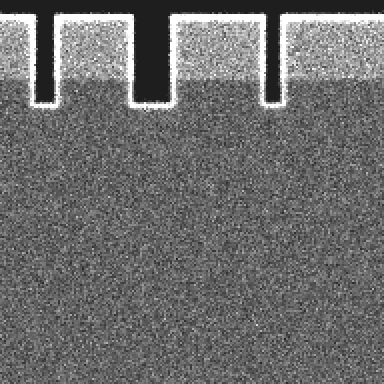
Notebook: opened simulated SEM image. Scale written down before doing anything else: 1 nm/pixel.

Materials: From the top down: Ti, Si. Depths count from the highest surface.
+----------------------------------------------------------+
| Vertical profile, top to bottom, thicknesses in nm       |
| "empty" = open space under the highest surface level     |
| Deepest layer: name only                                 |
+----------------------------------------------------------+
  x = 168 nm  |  empty 88, Si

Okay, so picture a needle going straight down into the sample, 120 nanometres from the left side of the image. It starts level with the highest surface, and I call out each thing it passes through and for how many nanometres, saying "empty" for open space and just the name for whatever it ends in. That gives Ti 64, Si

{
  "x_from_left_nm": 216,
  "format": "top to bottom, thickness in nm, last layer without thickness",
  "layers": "Ti 64, Si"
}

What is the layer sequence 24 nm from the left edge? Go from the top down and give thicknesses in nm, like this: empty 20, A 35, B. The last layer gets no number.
Ti 64, Si